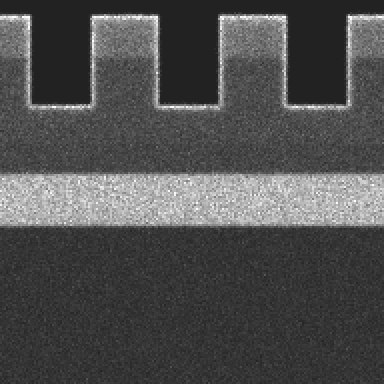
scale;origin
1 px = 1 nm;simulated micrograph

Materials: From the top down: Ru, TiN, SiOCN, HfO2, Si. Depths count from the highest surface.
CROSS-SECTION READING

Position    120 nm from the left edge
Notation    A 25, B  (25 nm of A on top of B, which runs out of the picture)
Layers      Ru 42, TiN 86, SiOCN 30, HfO2 52, Si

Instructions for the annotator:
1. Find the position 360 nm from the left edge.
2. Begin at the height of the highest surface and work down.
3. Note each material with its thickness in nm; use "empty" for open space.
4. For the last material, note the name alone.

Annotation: Ru 42, TiN 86, SiOCN 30, HfO2 52, Si